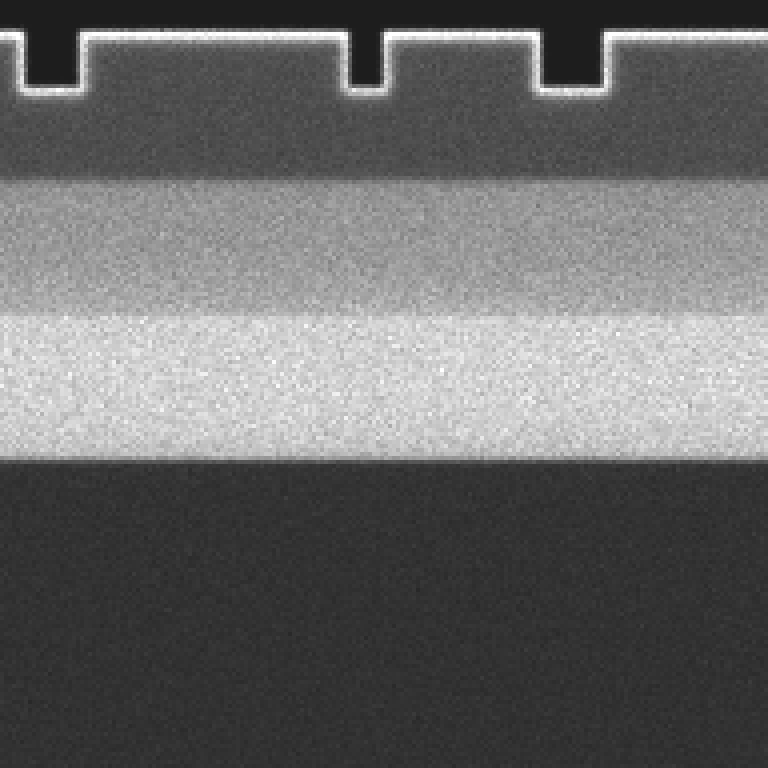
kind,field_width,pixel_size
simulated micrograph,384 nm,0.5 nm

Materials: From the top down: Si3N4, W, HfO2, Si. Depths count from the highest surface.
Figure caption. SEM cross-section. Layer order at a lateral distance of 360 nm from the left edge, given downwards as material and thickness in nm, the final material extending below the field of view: Si3N4 74, W 68, HfO2 72, Si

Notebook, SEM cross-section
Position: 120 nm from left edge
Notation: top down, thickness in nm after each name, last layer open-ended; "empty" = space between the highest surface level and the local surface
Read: Si3N4 74, W 68, HfO2 72, Si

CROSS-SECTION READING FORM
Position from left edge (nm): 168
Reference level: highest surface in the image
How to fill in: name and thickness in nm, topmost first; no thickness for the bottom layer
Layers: Si3N4 74, W 68, HfO2 72, Si